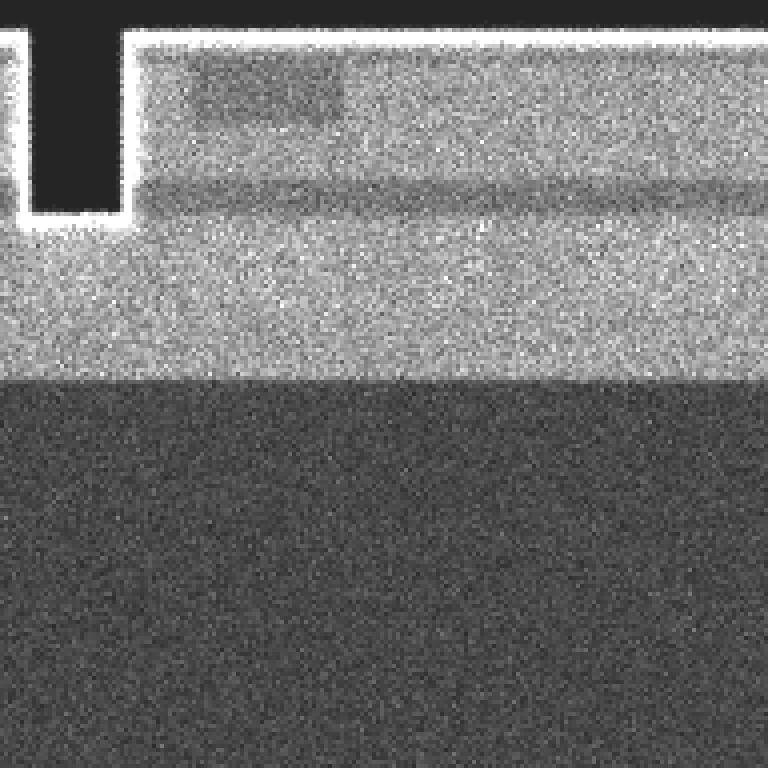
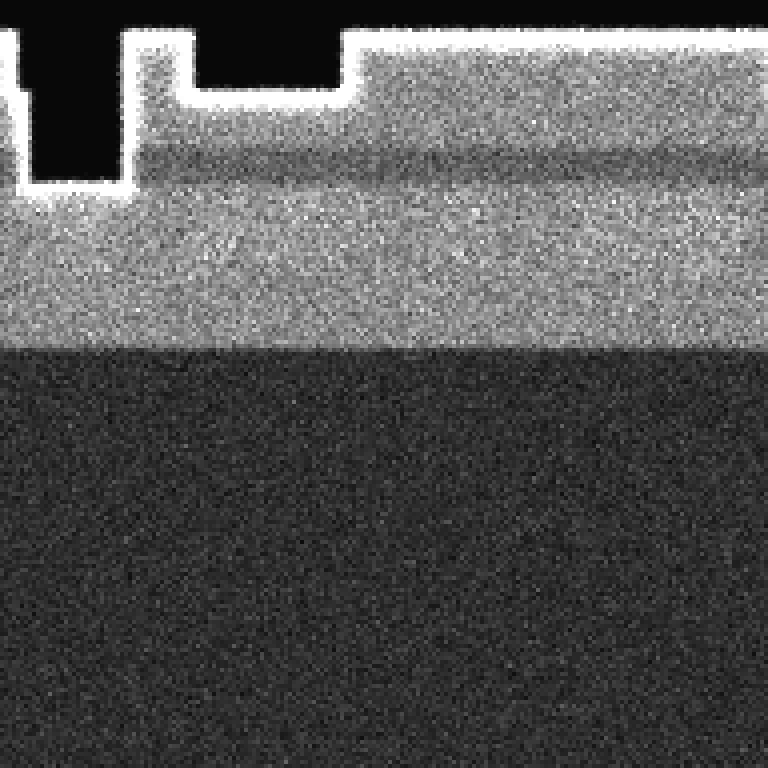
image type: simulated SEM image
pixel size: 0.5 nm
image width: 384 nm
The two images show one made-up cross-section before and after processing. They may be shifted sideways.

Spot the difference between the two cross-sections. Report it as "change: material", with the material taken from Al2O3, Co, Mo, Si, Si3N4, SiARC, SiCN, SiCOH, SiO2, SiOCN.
removed: SiARC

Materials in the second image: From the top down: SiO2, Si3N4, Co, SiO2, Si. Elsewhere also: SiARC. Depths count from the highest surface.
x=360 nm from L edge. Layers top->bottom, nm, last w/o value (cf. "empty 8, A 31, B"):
SiO2 58, Si3N4 18, Co 44, SiO2 38, Si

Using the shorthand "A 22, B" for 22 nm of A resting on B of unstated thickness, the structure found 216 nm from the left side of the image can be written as SiO2 58, Si3N4 18, Co 44, SiO2 38, Si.